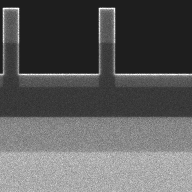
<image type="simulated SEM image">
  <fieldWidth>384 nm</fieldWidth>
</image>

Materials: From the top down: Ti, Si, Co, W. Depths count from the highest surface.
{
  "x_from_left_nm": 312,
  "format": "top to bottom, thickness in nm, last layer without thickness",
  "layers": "empty 132, Ti 26, Si 60, Co 70, W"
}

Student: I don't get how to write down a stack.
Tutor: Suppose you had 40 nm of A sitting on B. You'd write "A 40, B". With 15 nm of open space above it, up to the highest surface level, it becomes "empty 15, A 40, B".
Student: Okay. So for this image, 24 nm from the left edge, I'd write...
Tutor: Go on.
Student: Ti 70, Si 148, Co 70, W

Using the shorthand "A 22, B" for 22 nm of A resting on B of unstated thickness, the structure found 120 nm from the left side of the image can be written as empty 132, Ti 26, Si 60, Co 70, W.